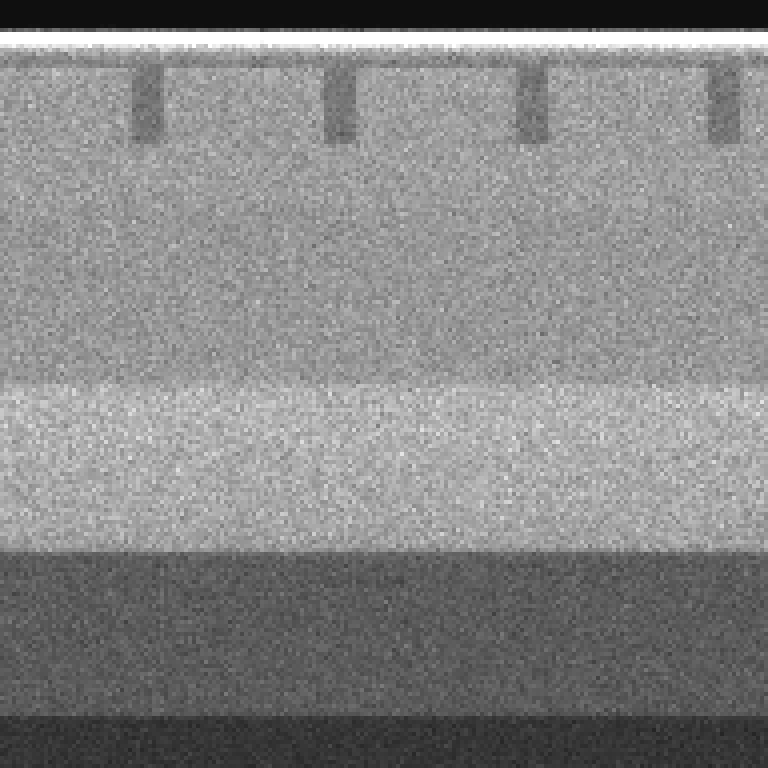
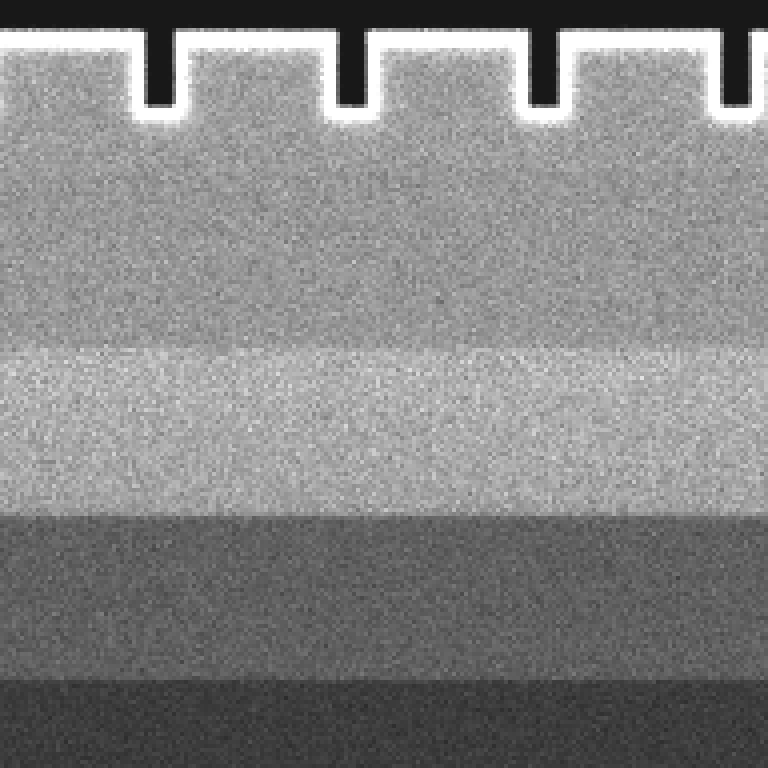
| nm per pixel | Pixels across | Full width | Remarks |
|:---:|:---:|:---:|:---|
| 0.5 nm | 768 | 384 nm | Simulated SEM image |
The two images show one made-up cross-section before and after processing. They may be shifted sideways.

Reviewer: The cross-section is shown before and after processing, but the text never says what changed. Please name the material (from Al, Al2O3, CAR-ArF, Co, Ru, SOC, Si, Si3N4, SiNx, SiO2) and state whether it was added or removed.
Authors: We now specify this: SOC, removed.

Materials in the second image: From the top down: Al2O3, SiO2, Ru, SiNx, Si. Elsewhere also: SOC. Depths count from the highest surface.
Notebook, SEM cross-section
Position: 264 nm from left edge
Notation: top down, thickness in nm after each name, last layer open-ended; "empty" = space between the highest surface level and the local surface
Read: empty 38, Al2O3 32, SiO2 88, Ru 84, SiNx 82, Si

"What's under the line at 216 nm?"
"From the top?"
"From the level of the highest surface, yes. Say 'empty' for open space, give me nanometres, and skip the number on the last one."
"Al2O3 70, SiO2 88, Ru 84, SiNx 82, Si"